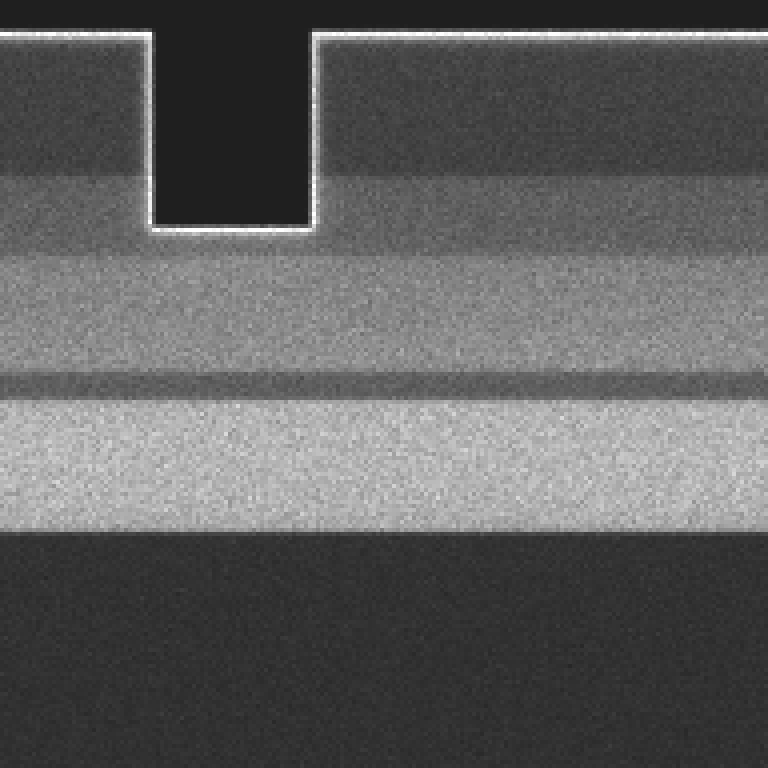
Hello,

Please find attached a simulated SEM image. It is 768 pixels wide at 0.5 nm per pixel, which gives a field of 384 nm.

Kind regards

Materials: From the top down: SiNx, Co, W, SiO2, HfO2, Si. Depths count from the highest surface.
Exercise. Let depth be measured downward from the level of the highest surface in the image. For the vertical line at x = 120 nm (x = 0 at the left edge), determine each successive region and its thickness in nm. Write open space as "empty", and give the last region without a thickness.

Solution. empty 98, Co 14, W 58, SiO2 14, HfO2 66, Si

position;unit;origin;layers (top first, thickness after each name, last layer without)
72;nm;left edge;SiNx 72, Co 40, W 58, SiO2 14, HfO2 66, Si